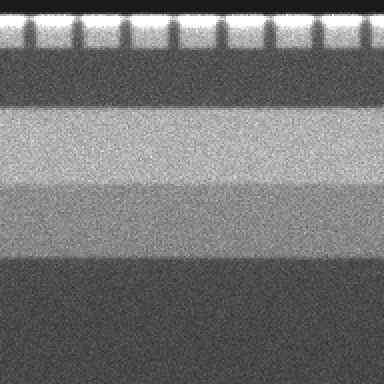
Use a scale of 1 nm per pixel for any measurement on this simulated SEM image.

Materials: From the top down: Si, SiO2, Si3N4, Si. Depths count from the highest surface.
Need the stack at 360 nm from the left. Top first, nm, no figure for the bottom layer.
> Si 92, SiO2 76, Si3N4 74, Si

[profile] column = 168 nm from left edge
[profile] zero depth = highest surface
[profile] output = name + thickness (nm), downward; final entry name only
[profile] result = Si 92, SiO2 76, Si3N4 74, Si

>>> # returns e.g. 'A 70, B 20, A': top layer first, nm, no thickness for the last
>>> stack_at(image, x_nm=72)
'Si 92, SiO2 76, Si3N4 74, Si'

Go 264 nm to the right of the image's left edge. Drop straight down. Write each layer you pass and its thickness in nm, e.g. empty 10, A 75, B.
Si 92, SiO2 76, Si3N4 74, Si